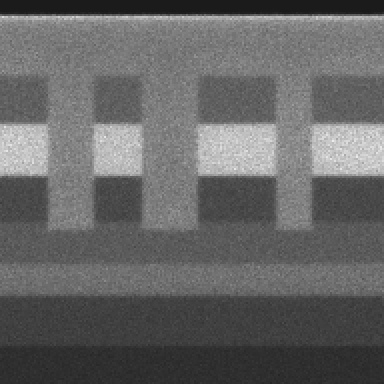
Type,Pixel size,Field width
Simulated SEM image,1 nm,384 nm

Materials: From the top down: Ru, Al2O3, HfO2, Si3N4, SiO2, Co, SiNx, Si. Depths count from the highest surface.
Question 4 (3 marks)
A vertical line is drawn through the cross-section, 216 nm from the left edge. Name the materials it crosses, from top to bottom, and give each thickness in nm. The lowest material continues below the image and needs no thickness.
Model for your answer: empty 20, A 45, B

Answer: Ru 60, Al2O3 48, HfO2 52, Si3N4 46, SiO2 42, Co 32, SiNx 50, Si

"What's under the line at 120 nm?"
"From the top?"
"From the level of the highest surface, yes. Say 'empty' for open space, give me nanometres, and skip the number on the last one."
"Ru 60, Al2O3 48, HfO2 52, Si3N4 46, SiO2 42, Co 32, SiNx 50, Si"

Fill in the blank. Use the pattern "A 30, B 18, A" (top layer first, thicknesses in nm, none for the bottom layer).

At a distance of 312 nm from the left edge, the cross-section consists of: Ru 60, Al2O3 48, HfO2 52, Si3N4 46, SiO2 42, Co 32, SiNx 50, Si